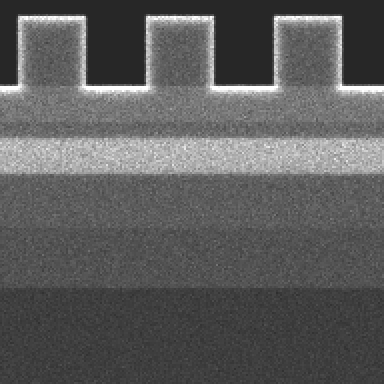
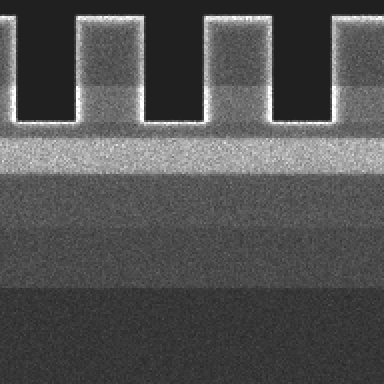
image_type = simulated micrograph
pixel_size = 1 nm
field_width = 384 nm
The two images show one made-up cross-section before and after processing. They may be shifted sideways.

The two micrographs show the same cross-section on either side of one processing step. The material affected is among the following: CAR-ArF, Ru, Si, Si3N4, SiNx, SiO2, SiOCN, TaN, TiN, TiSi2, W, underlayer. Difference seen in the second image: SiO2 removed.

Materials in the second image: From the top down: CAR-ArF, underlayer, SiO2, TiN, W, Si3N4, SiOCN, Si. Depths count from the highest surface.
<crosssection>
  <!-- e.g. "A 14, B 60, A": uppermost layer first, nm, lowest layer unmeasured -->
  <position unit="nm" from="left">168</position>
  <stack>empty 106, TiN 16, W 36, Si3N4 54, SiOCN 60, Si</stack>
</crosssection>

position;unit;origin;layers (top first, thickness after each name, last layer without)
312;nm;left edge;empty 106, TiN 16, W 36, Si3N4 54, SiOCN 60, Si